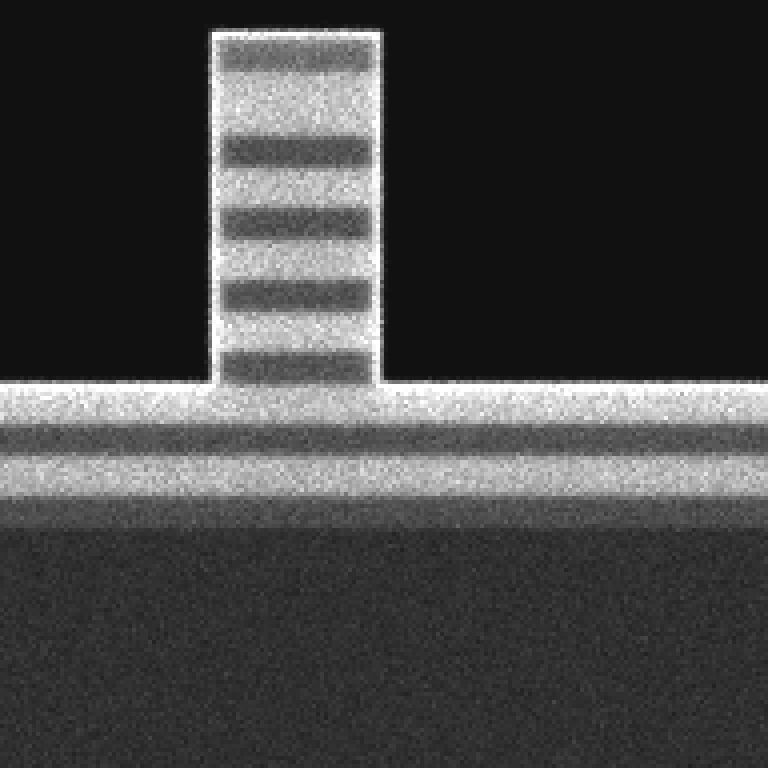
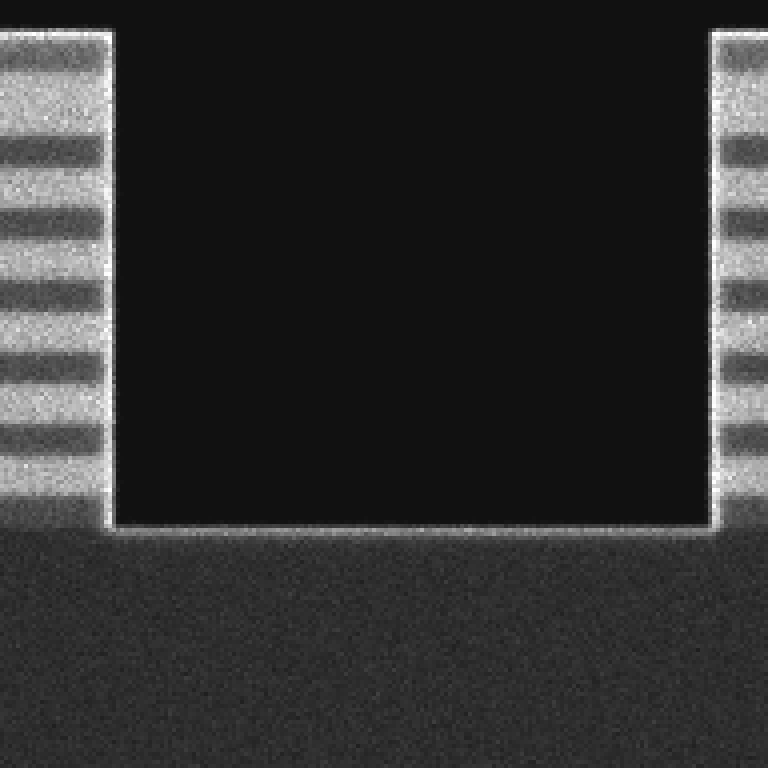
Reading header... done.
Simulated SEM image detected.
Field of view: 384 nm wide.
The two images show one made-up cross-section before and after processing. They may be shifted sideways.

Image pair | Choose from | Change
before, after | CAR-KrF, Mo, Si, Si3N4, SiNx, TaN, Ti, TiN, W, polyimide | SiNx and W (removed)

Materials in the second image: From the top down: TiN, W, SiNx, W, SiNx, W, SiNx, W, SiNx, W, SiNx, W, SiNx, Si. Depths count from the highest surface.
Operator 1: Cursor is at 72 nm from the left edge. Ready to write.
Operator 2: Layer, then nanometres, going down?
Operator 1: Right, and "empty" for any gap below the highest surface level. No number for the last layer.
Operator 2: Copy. empty 248, Si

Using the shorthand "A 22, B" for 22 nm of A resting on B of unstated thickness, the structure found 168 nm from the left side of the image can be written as empty 248, Si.